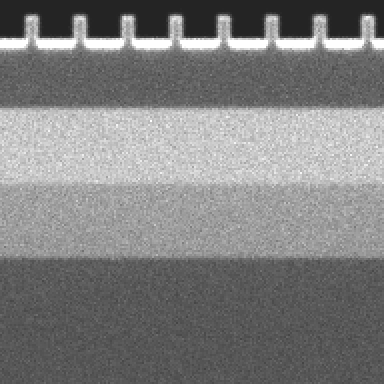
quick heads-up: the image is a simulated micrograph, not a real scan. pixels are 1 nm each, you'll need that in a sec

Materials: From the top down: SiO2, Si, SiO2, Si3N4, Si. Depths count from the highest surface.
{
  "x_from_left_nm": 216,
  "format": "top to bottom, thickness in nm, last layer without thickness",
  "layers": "empty 24, SiO2 8, Si 60, SiO2 76, Si3N4 74, Si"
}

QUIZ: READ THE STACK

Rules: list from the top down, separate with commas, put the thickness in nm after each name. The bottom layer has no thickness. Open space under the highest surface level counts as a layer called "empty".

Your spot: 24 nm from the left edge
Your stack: empty 24, SiO2 8, Si 60, SiO2 76, Si3N4 74, Si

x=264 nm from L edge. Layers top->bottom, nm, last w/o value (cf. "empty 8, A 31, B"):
empty 24, SiO2 8, Si 60, SiO2 76, Si3N4 74, Si